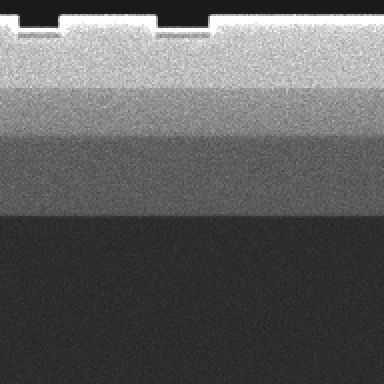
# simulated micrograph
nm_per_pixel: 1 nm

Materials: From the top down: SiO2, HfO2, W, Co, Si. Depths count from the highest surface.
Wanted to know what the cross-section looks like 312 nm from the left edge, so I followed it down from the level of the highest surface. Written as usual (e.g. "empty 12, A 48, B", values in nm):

HfO2 72, W 48, Co 80, Si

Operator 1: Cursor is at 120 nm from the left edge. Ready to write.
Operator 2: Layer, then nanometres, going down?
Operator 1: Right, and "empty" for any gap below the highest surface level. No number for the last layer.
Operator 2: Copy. HfO2 72, W 48, Co 80, Si